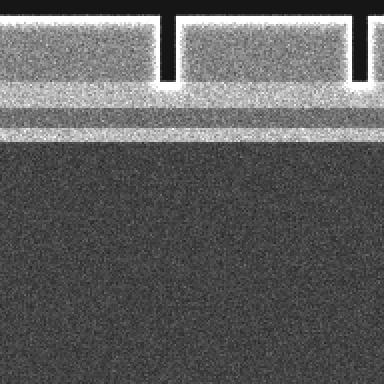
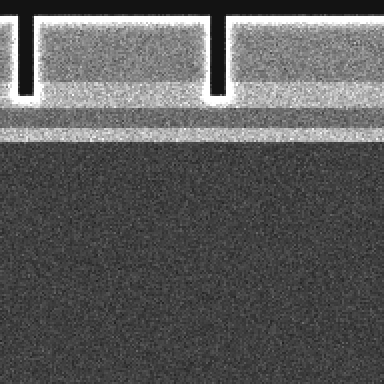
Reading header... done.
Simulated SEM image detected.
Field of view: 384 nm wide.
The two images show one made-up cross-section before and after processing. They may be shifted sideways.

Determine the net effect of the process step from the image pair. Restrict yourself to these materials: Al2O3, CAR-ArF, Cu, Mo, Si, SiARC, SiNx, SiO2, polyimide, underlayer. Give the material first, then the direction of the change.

SiO2: removed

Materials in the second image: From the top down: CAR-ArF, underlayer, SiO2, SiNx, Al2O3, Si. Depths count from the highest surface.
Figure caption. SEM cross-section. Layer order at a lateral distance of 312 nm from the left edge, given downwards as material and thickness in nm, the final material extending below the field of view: CAR-ArF 40, underlayer 26, SiO2 26, SiNx 20, Al2O3 14, Si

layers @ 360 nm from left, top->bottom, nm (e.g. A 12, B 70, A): CAR-ArF 40, underlayer 26, SiO2 26, SiNx 20, Al2O3 14, Si